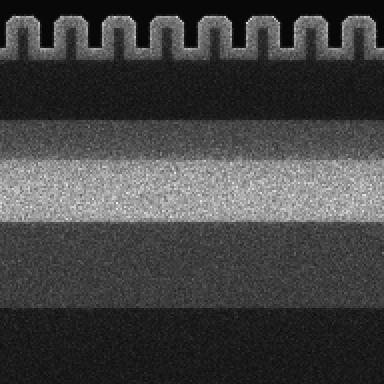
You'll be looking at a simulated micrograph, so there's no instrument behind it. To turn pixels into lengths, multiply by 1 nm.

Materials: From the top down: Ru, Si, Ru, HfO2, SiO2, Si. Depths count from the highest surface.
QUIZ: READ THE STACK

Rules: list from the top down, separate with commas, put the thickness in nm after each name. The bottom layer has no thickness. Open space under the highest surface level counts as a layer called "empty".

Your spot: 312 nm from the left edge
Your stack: Ru 12, Si 92, Ru 40, HfO2 62, SiO2 86, Si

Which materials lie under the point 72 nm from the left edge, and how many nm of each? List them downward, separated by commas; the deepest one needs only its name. Ru 12, Si 92, Ru 40, HfO2 62, SiO2 86, Si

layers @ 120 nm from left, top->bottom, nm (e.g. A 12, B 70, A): Ru 12, Si 92, Ru 40, HfO2 62, SiO2 86, Si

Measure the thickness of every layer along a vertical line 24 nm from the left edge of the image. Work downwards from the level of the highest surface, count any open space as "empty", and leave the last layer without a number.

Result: Ru 12, Si 92, Ru 40, HfO2 62, SiO2 86, Si